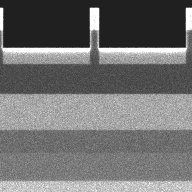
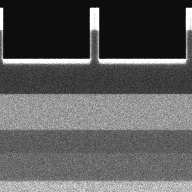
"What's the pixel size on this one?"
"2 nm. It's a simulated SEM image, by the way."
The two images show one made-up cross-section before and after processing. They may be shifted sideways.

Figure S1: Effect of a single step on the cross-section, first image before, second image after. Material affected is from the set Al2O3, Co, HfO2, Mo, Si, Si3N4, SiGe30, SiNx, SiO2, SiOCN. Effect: removed SiO2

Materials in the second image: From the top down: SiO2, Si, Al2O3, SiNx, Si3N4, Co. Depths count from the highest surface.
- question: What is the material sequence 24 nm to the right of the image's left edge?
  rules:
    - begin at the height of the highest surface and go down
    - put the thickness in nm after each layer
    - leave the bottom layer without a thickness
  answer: empty 102, SiO2 10, Si 60, Al2O3 72, SiNx 46, Si3N4 56, Co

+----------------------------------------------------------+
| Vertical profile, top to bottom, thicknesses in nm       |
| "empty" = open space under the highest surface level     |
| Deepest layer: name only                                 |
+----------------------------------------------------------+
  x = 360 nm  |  empty 102, SiO2 10, Si 60, Al2O3 72, SiNx 46, Si3N4 56, Co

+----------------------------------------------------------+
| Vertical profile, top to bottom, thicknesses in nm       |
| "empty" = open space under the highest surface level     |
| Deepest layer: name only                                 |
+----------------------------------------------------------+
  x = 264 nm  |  empty 102, SiO2 10, Si 60, Al2O3 72, SiNx 46, Si3N4 56, Co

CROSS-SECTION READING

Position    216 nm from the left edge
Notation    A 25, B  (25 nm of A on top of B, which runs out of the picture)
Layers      empty 102, SiO2 10, Si 60, Al2O3 72, SiNx 46, Si3N4 56, Co